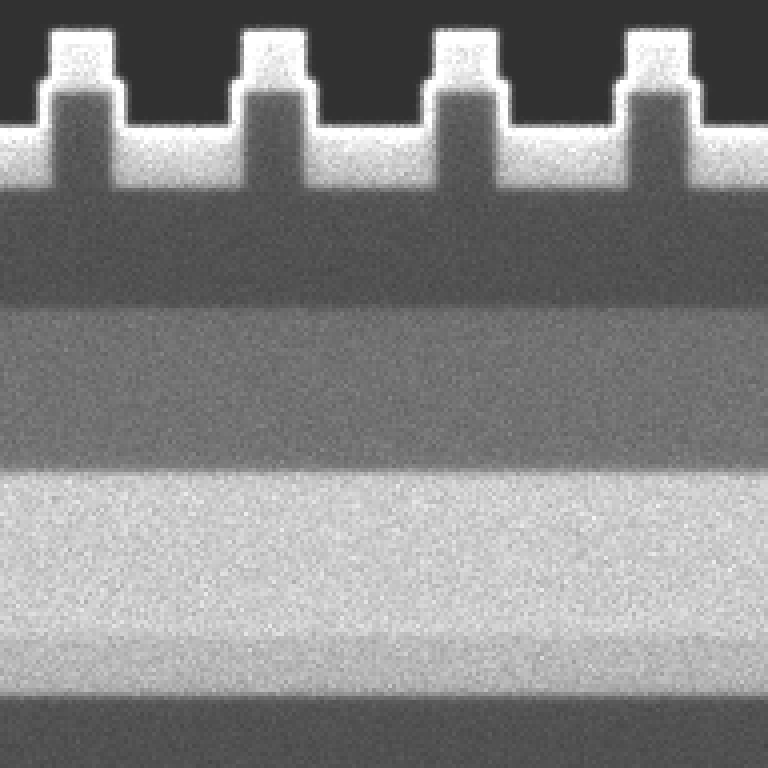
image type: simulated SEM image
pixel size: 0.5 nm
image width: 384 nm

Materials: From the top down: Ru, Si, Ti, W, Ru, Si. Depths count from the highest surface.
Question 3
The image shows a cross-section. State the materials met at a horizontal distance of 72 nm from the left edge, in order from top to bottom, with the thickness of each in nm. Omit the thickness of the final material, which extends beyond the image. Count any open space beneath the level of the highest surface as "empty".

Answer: empty 48, Ru 30, Si 60, Ti 82, W 82, Ru 30, Si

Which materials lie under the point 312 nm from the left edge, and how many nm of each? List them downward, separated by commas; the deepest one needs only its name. empty 24, Ru 54, Si 60, Ti 82, W 82, Ru 30, Si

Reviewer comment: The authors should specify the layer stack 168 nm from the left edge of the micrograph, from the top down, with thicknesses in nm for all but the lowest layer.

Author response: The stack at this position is empty 48, Ru 30, Si 60, Ti 82, W 82, Ru 30, Si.